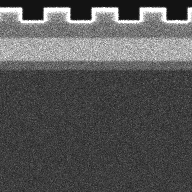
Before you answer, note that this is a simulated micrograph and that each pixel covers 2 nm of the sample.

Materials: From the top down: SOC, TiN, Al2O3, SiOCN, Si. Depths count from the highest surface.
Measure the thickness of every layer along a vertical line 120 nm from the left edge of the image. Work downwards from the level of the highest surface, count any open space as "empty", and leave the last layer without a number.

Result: SOC 26, TiN 34, Al2O3 46, SiOCN 18, Si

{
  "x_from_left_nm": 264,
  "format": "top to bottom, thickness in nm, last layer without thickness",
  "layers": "empty 26, TiN 34, Al2O3 46, SiOCN 18, Si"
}